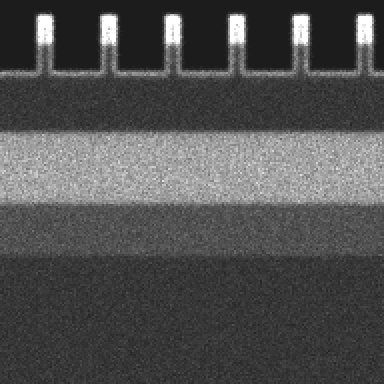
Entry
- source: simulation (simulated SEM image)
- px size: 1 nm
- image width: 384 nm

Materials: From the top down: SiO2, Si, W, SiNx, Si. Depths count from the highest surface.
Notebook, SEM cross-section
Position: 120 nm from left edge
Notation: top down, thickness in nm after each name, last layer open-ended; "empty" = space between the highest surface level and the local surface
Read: empty 56, Si 60, W 72, SiNx 52, Si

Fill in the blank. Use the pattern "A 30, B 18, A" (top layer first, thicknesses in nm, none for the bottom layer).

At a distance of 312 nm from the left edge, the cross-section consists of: empty 56, Si 60, W 72, SiNx 52, Si